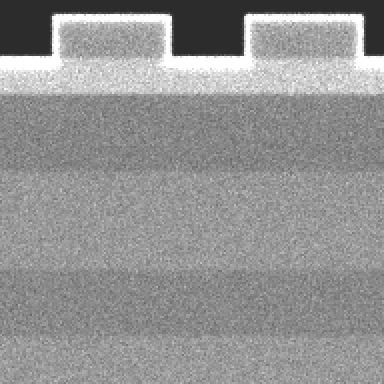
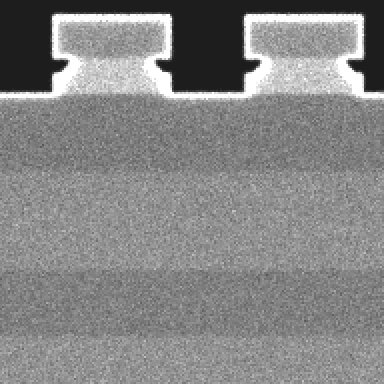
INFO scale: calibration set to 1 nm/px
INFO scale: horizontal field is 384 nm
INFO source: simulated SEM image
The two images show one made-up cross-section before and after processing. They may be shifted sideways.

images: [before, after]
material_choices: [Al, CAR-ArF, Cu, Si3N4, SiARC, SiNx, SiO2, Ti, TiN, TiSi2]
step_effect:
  removed: SiO2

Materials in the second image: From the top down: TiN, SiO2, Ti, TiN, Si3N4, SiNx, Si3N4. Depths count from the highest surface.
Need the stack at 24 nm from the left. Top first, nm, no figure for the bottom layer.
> empty 78, Ti 78, TiN 42, Si3N4 56, SiNx 66, Si3N4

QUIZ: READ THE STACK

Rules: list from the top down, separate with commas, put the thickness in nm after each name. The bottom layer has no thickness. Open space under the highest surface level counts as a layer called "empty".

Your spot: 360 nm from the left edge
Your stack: TiN 42, empty 16, SiO2 20, Ti 78, TiN 42, Si3N4 56, SiNx 66, Si3N4